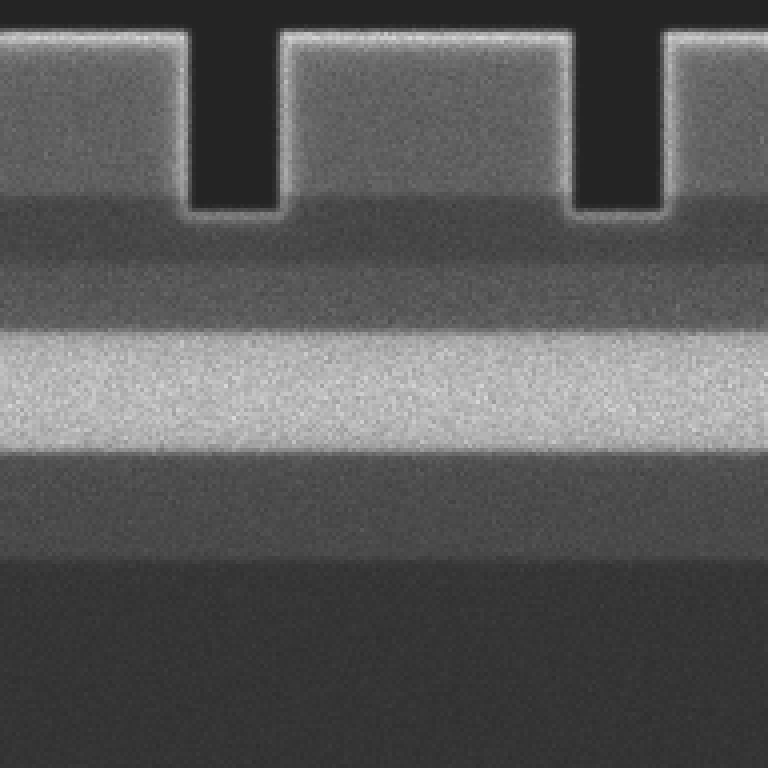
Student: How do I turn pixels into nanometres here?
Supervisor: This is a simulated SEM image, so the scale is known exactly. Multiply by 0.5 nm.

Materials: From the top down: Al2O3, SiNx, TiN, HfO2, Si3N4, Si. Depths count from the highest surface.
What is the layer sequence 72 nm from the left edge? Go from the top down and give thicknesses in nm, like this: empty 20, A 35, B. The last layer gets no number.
Al2O3 82, SiNx 34, TiN 34, HfO2 60, Si3N4 54, Si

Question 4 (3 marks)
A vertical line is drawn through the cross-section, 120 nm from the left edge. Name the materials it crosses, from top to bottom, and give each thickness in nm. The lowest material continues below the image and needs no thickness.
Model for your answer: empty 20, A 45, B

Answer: empty 90, SiNx 26, TiN 34, HfO2 60, Si3N4 54, Si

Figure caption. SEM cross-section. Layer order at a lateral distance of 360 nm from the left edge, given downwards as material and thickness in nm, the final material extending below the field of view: Al2O3 82, SiNx 34, TiN 34, HfO2 60, Si3N4 54, Si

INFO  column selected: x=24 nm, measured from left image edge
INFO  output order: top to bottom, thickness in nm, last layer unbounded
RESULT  Al2O3 82, SiNx 34, TiN 34, HfO2 60, Si3N4 54, Si